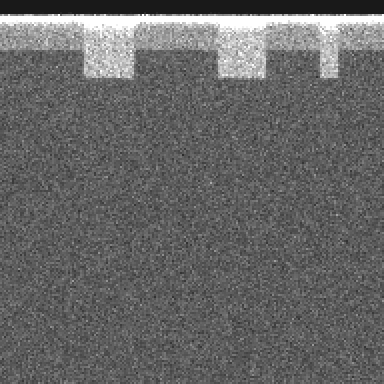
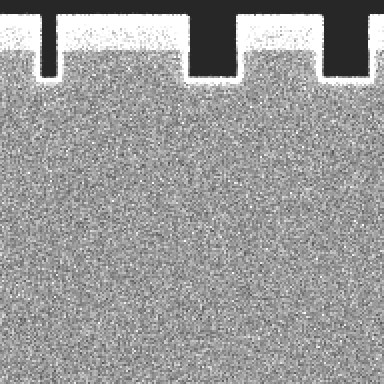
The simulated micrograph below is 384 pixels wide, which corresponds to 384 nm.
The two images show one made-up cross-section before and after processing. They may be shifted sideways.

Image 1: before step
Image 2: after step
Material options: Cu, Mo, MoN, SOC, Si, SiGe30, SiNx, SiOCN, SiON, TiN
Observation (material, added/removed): SOC, removed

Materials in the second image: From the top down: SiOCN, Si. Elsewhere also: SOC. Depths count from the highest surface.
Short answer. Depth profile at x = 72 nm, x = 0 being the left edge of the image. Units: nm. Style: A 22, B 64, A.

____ SiOCN 34, Si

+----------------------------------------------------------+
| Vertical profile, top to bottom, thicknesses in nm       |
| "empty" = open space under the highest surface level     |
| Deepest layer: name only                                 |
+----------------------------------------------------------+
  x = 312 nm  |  SiOCN 34, Si